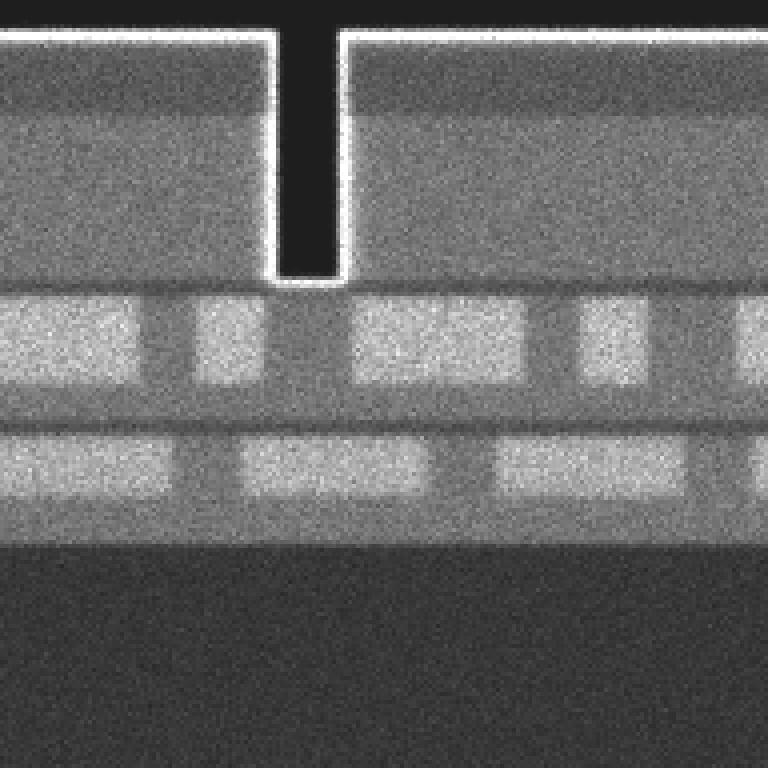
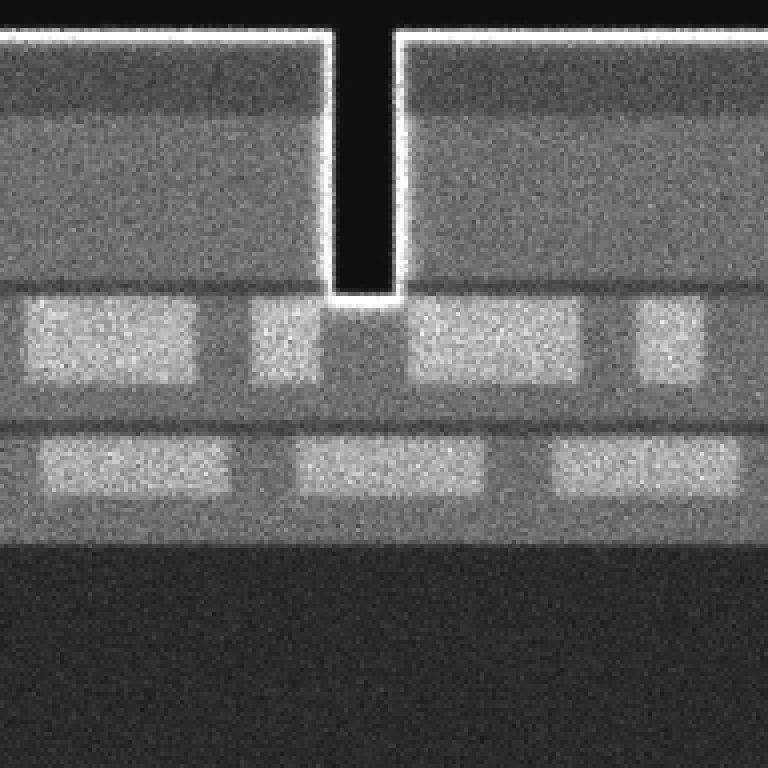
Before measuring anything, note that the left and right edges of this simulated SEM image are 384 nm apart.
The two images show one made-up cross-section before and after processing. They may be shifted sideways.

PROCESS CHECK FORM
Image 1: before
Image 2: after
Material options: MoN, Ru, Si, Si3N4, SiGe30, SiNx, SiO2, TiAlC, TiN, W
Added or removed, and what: removed, SiNx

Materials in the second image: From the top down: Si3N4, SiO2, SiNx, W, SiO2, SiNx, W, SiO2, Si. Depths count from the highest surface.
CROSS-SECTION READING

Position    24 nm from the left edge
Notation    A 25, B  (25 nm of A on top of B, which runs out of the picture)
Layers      Si3N4 42, SiO2 82, SiNx 8, W 44, SiO2 18, SiNx 8, W 30, SiO2 24, Si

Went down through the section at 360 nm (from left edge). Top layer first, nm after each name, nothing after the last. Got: Si3N4 42, SiO2 82, SiNx 8, SiO2 62, SiNx 8, W 30, SiO2 24, Si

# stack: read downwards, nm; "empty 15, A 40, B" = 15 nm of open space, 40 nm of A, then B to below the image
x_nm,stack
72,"Si3N4 42, SiO2 82, SiNx 8, W 44, SiO2 18, SiNx 8, W 30, SiO2 24, Si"